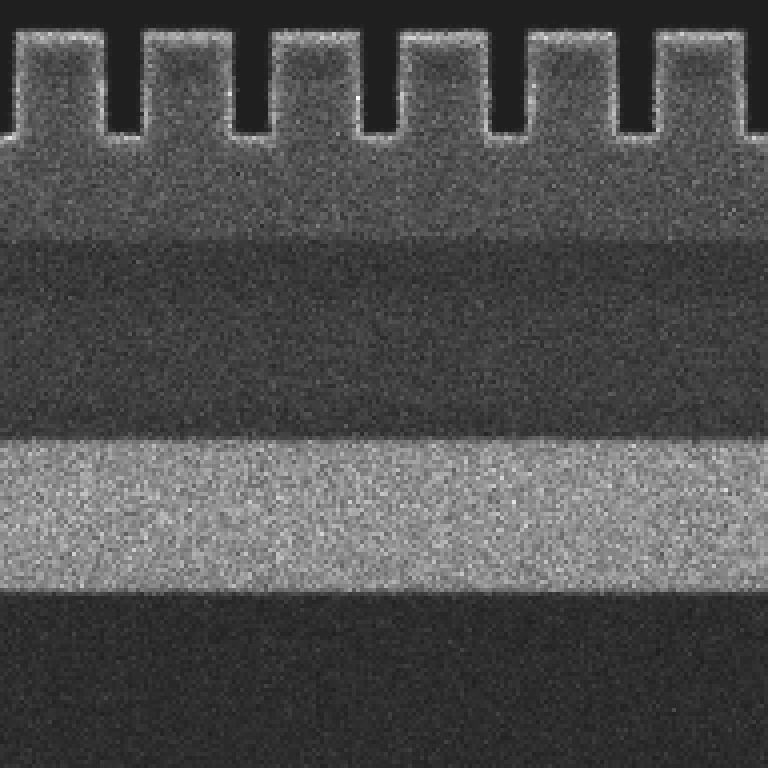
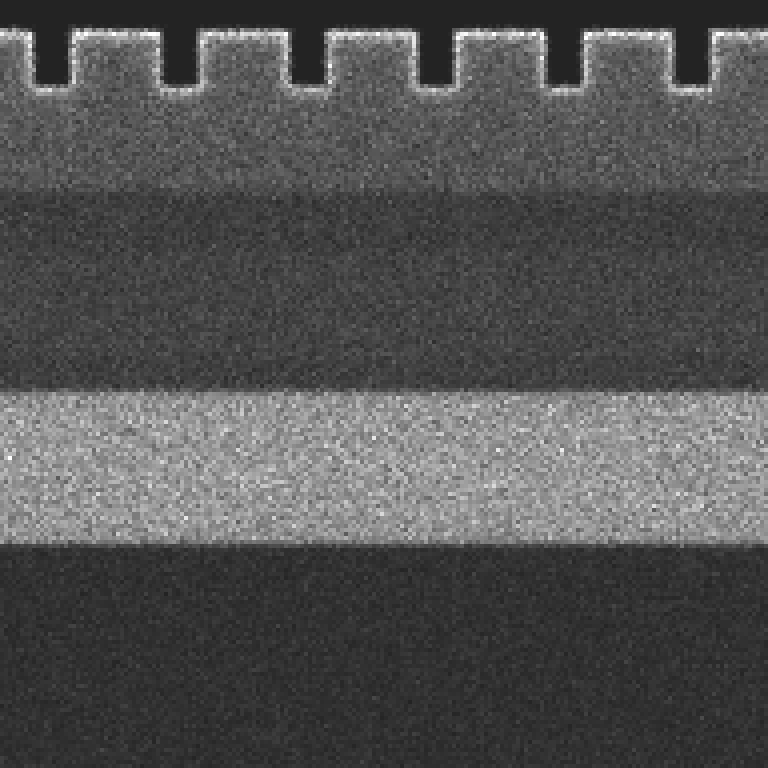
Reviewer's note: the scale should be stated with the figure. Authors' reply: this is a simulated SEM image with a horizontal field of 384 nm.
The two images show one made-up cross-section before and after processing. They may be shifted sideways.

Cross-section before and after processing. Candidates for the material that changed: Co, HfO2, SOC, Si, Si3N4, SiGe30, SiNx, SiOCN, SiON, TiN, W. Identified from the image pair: SOC (removed).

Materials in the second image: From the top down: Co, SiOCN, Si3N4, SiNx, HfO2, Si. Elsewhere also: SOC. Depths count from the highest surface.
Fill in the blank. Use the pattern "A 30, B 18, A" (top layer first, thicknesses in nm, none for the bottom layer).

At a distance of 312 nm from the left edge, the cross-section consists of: Co 80, SiOCN 30, Si3N4 52, SiNx 18, HfO2 76, Si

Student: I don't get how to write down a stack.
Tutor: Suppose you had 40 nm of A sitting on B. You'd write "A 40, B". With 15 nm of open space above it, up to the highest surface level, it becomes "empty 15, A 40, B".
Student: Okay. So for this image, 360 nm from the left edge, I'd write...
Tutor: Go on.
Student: Co 80, SiOCN 30, Si3N4 52, SiNx 18, HfO2 76, Si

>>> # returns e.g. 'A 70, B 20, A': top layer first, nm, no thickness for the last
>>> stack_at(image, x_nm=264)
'Co 80, SiOCN 30, Si3N4 52, SiNx 18, HfO2 76, Si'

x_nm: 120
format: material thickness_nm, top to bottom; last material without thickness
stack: Co 80, SiOCN 30, Si3N4 52, SiNx 18, HfO2 76, Si